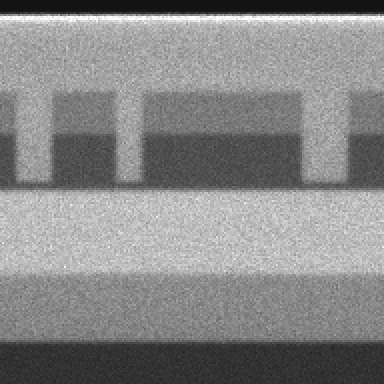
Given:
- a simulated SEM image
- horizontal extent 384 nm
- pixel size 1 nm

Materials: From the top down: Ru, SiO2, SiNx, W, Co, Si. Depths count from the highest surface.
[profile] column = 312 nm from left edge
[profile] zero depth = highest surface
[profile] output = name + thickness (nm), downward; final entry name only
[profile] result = Ru 166, SiNx 8, W 84, Co 68, Si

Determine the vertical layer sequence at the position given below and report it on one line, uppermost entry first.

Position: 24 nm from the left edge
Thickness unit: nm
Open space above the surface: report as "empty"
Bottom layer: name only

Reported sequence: Ru 166, SiNx 8, W 84, Co 68, Si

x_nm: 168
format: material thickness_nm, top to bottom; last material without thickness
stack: Ru 76, SiO2 42, SiNx 56, W 84, Co 68, Si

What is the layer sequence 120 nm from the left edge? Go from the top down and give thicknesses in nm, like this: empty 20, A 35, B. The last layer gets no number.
Ru 166, SiNx 8, W 84, Co 68, Si